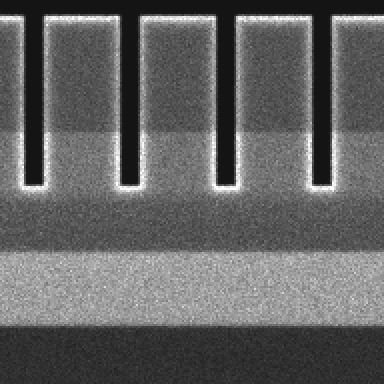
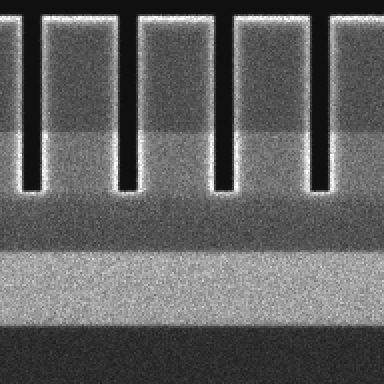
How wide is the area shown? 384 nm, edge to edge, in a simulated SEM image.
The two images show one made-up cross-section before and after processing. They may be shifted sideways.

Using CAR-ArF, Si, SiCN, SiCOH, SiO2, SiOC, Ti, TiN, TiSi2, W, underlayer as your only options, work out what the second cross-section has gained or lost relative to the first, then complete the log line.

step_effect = removed SiO2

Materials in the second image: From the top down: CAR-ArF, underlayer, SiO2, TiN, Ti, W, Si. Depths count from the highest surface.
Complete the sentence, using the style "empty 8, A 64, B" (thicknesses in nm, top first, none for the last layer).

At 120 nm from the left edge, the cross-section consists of empty 176, TiN 8, Ti 52, W 74, Si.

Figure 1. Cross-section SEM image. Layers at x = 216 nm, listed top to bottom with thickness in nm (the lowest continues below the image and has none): empty 176, TiN 8, Ti 52, W 74, Si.